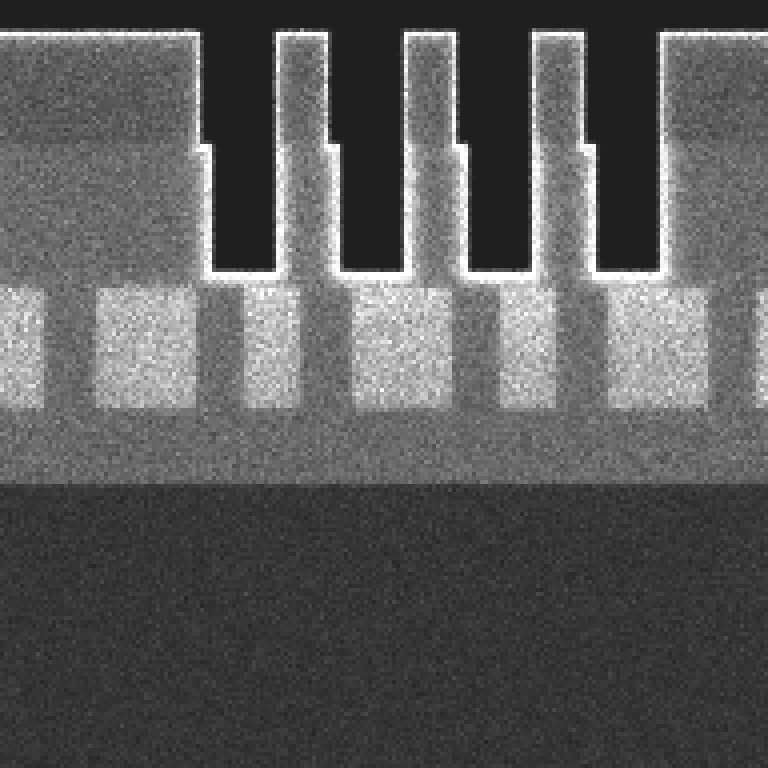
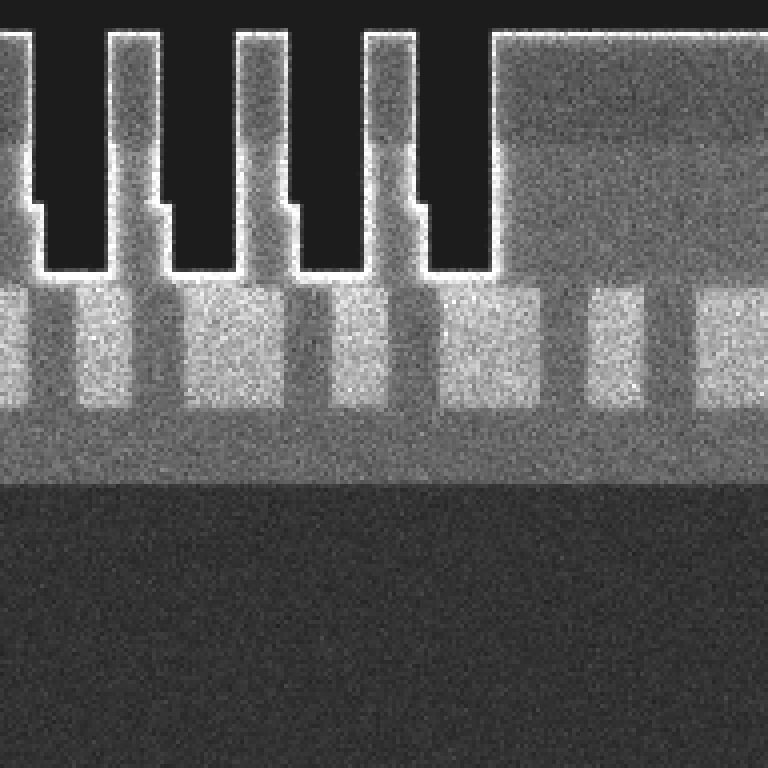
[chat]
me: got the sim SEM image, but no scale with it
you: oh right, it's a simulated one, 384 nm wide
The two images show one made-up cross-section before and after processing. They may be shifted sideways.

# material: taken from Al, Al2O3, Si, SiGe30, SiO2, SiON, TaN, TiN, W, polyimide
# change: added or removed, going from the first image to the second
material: SiO2
change: removed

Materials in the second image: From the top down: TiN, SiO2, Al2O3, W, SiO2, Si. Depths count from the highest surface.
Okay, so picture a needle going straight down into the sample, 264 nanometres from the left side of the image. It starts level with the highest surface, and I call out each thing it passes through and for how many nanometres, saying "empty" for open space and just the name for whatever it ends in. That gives TiN 56, SiO2 64, Al2O3 8, W 60, SiO2 38, Si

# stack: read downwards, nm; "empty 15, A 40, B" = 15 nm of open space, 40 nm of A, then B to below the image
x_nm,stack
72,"TiN 56, SiO2 64, Al2O3 8, SiO2 98, Si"